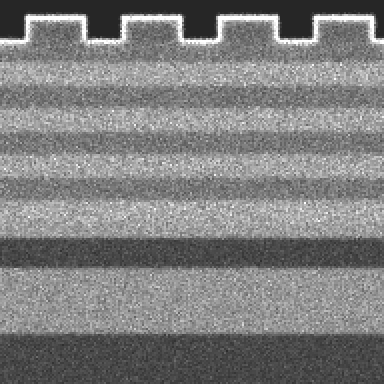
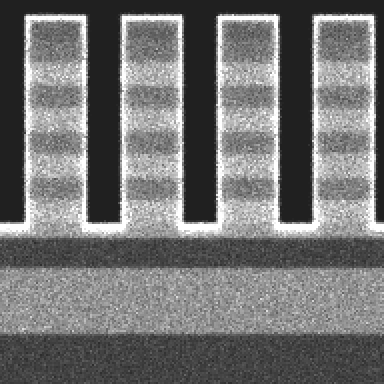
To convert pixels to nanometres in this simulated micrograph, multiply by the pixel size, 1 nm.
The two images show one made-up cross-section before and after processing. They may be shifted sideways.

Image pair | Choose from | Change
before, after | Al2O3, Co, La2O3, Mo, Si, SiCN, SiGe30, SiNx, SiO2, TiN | Co and TiN (removed)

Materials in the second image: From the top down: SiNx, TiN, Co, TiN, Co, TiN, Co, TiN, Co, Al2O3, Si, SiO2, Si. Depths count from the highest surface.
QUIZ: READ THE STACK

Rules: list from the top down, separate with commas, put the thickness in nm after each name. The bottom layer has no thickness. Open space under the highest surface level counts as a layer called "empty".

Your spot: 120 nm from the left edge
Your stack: empty 208, Al2O3 14, Si 30, SiO2 66, Si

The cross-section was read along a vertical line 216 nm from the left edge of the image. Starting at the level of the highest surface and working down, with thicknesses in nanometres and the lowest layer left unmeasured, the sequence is empty 208, Al2O3 14, Si 30, SiO2 66, Si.